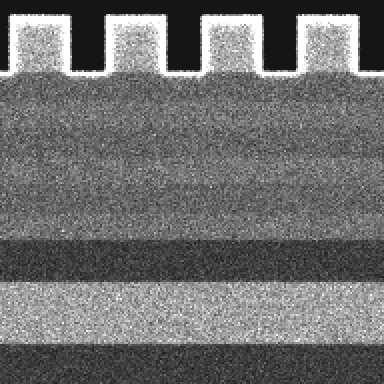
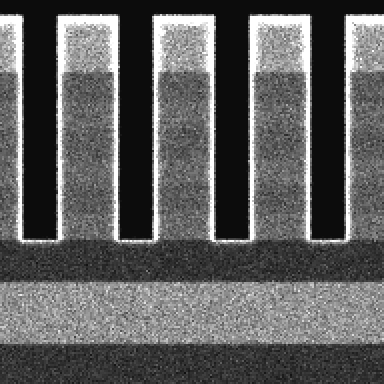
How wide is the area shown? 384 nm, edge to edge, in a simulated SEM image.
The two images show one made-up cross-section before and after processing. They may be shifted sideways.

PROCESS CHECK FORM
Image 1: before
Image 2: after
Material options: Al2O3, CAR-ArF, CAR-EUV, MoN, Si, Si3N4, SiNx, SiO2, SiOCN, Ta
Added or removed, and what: removed, Si3N4 and SiNx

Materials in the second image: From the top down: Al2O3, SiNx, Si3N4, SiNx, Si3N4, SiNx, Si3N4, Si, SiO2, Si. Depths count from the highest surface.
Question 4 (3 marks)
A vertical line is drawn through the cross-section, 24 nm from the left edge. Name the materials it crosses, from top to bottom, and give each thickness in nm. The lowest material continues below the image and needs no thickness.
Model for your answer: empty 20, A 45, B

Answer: empty 224, Si 42, SiO2 62, Si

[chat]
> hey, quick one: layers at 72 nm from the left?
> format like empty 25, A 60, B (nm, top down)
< Al2O3 56, SiNx 30, Si3N4 26, SiNx 30, Si3N4 26, SiNx 30, Si3N4 26, Si 42, SiO2 62, Si